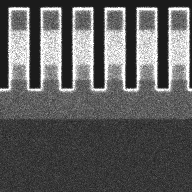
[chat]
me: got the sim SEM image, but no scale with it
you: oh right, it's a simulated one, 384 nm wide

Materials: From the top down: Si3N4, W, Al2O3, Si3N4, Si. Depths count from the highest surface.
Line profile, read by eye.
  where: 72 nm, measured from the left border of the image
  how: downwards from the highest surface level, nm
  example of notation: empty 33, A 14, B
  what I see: empty 162, Si3N4 60, Si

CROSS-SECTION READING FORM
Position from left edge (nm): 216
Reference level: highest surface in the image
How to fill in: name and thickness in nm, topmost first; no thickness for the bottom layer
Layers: Si3N4 44, W 70, Al2O3 30, Si3N4 78, Si